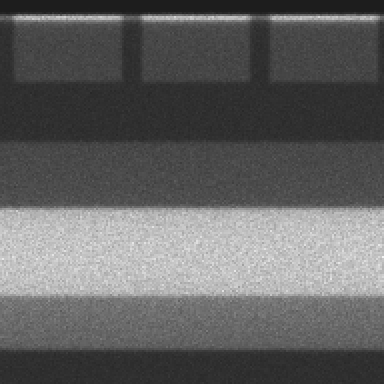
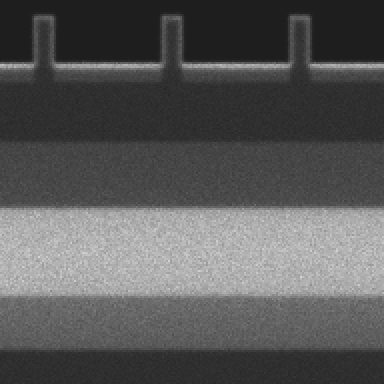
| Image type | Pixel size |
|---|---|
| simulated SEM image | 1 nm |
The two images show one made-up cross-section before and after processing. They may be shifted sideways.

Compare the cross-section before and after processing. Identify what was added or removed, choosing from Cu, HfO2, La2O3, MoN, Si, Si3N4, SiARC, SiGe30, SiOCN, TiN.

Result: Si3N4 removed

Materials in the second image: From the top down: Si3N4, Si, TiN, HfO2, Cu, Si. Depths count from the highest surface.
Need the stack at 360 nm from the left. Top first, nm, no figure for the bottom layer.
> empty 48, Si3N4 18, Si 60, TiN 66, HfO2 88, Cu 54, Si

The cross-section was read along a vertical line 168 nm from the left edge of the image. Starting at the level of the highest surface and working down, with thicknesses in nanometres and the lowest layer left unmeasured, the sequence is Si 126, TiN 66, HfO2 88, Cu 54, Si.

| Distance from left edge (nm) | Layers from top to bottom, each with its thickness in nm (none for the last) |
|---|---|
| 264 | empty 48, Si3N4 18, Si 60, TiN 66, HfO2 88, Cu 54, Si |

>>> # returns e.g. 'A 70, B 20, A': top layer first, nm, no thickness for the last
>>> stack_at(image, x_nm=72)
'empty 48, Si3N4 18, Si 60, TiN 66, HfO2 88, Cu 54, Si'